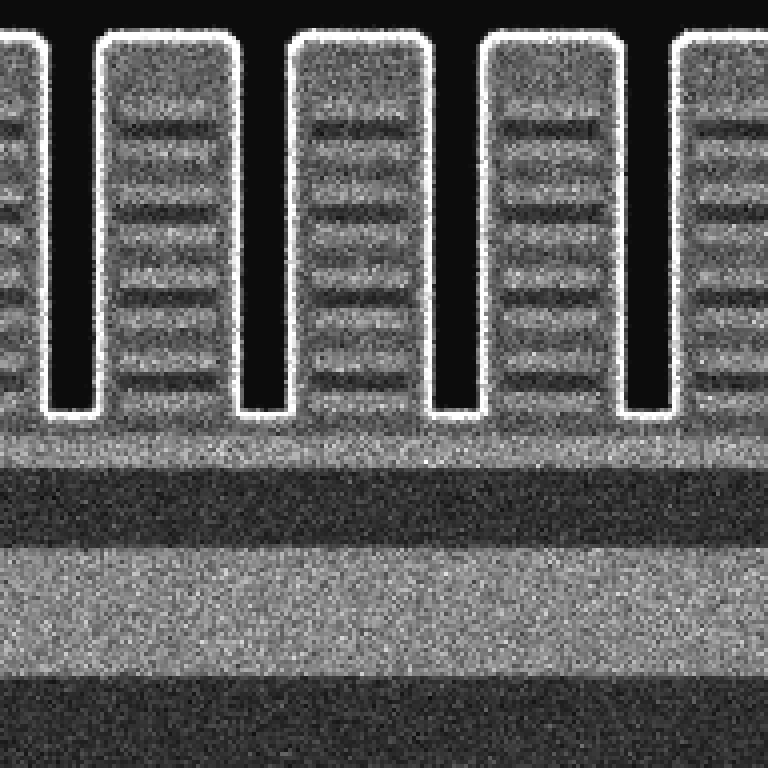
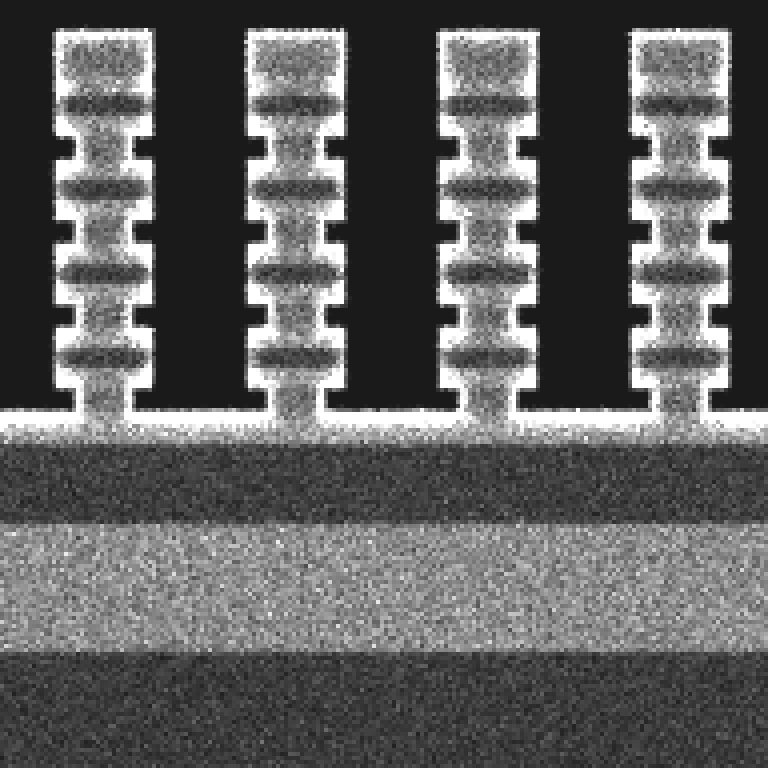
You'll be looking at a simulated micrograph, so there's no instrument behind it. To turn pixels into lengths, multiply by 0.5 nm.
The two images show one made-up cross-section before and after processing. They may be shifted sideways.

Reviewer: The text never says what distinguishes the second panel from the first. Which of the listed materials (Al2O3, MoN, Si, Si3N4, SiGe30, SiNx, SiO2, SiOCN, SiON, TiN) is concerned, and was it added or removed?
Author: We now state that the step removed SiNx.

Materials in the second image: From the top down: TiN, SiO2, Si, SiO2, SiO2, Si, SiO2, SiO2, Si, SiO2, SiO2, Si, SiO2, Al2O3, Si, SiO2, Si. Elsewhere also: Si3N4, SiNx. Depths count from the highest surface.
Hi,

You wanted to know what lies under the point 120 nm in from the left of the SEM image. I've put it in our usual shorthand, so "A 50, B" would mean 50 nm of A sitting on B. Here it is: empty 190, Al2O3 16, Si 40, SiO2 64, Si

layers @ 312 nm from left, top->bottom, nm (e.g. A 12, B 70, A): empty 190, Al2O3 16, Si 40, SiO2 64, Si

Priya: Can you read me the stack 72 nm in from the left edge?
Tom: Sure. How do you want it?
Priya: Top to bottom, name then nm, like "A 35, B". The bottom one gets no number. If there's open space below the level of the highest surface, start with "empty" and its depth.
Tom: TiN 22, SiO2 10, Si 10, SiO2 10, empty 12, SiO2 10, Si 10, SiO2 10, empty 12, SiO2 10, Si 10, SiO2 10, empty 12, SiO2 10, Si 10, SiO2 10, empty 12, Al2O3 16, Si 40, SiO2 64, Si